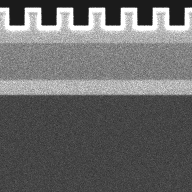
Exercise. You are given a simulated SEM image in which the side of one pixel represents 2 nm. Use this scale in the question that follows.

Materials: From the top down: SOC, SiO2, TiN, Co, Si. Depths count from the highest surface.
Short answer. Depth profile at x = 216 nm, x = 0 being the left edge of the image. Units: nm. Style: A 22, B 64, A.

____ empty 36, SiO2 34, TiN 74, Co 30, Si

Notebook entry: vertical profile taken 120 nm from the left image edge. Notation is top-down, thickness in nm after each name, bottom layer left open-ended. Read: SOC 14, SiO2 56, TiN 74, Co 30, Si